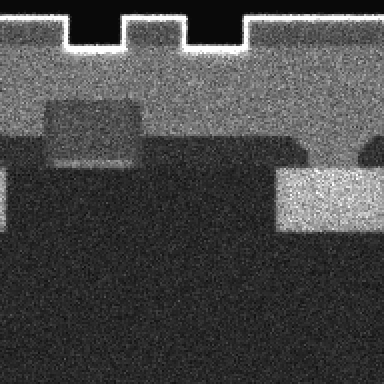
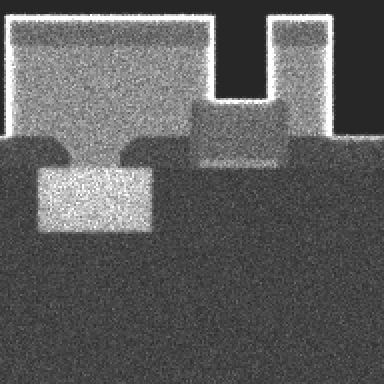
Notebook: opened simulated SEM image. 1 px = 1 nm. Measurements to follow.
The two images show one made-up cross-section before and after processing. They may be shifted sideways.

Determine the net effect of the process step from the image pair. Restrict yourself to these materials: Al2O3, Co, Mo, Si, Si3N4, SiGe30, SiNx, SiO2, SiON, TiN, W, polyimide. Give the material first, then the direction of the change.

SiO2: removed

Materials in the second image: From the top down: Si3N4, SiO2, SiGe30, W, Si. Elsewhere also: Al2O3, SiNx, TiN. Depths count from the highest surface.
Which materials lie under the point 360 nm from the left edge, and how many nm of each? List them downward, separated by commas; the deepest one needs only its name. empty 120, SiGe30 32, Si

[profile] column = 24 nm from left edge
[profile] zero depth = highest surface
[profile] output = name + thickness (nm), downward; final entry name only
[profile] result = Si3N4 30, SiO2 90, SiGe30 32, Si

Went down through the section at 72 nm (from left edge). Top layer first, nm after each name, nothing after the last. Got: Si3N4 30, SiO2 122, W 64, Si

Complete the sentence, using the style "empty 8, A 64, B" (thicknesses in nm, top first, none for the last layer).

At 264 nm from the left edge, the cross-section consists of empty 84, TiN 60, Al2O3 8, Si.